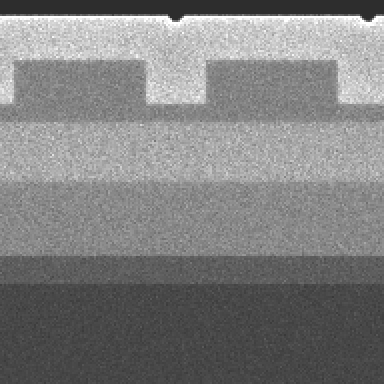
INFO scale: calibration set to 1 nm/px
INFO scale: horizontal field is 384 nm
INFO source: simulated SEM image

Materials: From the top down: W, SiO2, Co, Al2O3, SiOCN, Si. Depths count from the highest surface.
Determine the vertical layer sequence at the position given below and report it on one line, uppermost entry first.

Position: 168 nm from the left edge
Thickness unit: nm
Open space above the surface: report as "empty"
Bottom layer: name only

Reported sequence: empty 2, W 86, SiO2 18, Co 60, Al2O3 74, SiOCN 28, Si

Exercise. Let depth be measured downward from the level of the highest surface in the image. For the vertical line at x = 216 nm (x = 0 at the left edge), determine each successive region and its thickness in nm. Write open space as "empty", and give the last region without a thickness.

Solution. W 44, SiO2 62, Co 60, Al2O3 74, SiOCN 28, Si